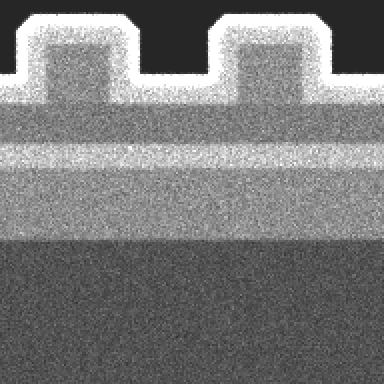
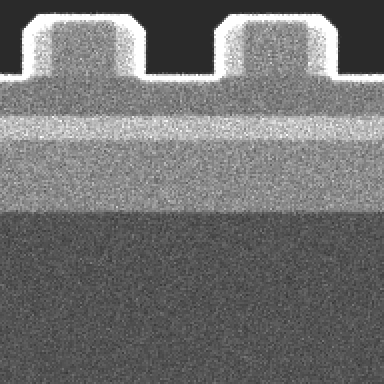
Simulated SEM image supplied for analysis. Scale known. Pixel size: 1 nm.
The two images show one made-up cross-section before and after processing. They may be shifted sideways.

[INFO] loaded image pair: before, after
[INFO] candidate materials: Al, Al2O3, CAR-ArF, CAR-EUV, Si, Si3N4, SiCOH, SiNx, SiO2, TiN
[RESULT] removed Al2O3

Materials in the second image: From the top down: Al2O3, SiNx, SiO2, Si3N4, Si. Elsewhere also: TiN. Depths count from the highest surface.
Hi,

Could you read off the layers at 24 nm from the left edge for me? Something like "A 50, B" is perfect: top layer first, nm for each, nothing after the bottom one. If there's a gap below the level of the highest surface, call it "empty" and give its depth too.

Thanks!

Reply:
empty 14, Al2O3 46, SiNx 40, SiO2 24, Si3N4 72, Si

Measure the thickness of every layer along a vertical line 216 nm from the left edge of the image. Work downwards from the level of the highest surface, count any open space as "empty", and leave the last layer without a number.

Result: empty 14, Al2O3 46, SiNx 40, SiO2 24, Si3N4 72, Si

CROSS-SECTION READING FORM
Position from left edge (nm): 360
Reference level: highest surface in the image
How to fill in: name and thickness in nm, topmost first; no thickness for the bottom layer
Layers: empty 60, SiNx 40, SiO2 24, Si3N4 72, Si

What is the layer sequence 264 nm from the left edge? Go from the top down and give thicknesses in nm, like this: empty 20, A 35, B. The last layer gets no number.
TiN 60, SiNx 40, SiO2 24, Si3N4 72, Si